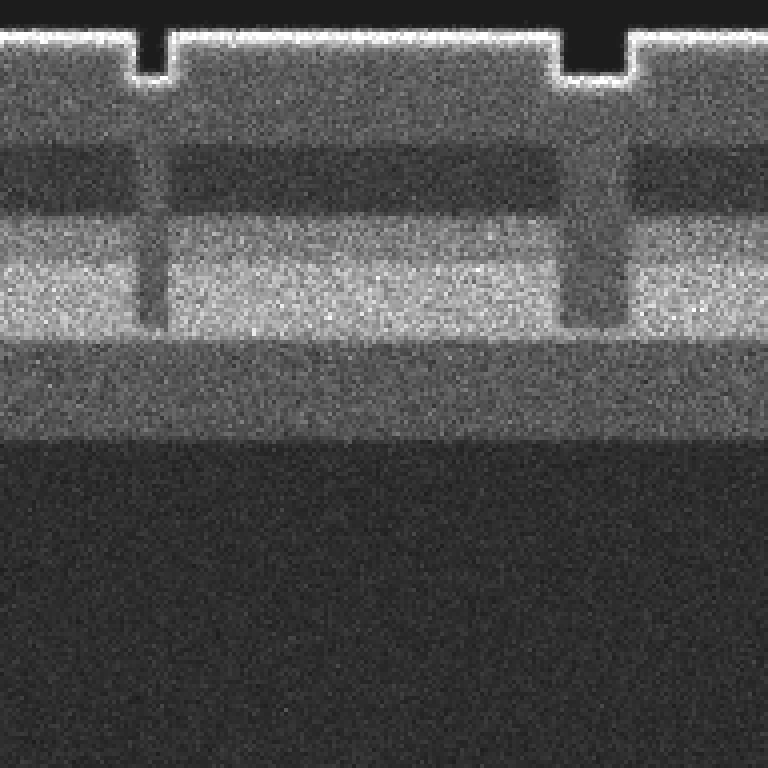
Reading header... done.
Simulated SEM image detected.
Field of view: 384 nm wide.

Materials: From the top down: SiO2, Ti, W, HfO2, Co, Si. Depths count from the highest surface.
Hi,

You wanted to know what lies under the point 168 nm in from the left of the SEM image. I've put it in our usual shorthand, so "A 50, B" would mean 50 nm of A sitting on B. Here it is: SiO2 56, Ti 36, W 24, HfO2 38, Co 50, Si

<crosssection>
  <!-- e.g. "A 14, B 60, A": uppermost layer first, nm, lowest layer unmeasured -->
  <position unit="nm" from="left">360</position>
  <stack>SiO2 56, Ti 36, W 24, HfO2 38, Co 50, Si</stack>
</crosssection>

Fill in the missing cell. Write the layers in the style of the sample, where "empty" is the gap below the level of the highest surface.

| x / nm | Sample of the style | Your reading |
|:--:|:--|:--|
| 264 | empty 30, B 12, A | SiO2 56, Ti 36, W 24, HfO2 38, Co 50, Si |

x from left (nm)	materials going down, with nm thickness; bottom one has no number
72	empty 22, SiO2 126, HfO2 6, Co 50, Si